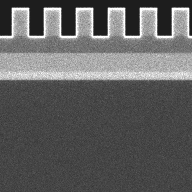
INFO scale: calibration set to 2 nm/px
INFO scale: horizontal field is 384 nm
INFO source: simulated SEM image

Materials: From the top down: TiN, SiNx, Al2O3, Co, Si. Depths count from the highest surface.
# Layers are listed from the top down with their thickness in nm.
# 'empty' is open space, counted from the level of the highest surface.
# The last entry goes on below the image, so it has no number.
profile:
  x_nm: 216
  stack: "TiN 56, SiNx 34, Al2O3 38, Co 16, Si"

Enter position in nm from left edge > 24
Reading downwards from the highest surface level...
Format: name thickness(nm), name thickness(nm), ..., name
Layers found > TiN 56, SiNx 34, Al2O3 38, Co 16, Si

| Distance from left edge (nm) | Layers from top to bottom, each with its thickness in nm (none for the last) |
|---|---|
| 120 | TiN 56, SiNx 34, Al2O3 38, Co 16, Si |